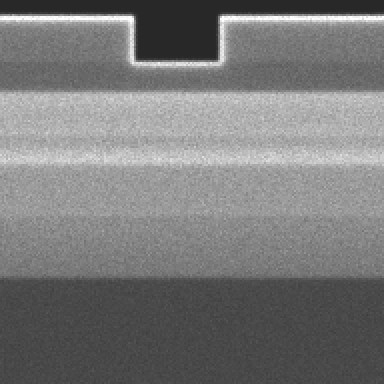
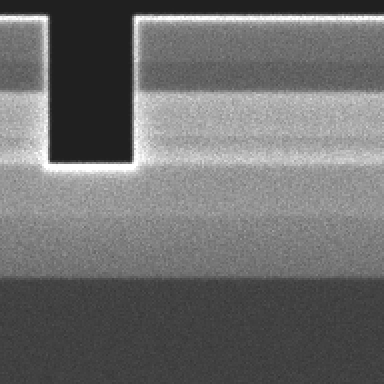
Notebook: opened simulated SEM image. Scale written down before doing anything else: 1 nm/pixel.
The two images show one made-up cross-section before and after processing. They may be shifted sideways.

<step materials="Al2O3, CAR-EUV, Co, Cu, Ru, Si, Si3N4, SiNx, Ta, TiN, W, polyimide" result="removed Co and Ru and SiNx and W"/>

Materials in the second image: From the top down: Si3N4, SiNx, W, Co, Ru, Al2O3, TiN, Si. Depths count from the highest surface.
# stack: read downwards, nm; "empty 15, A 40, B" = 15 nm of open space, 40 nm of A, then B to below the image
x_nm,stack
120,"empty 148, Al2O3 52, TiN 62, Si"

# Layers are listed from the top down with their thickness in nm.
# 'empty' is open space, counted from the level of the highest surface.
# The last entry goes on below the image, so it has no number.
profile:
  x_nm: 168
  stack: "Si3N4 46, SiNx 30, W 44, Co 12, Ru 16, Al2O3 52, TiN 62, Si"